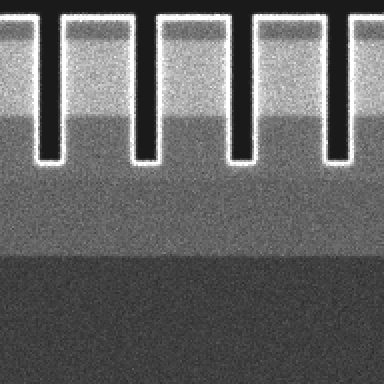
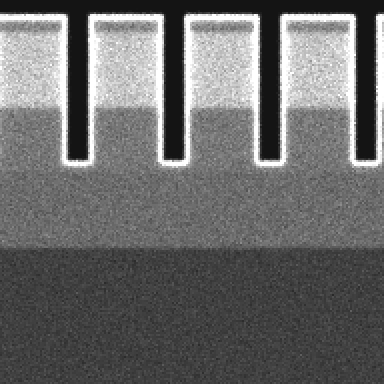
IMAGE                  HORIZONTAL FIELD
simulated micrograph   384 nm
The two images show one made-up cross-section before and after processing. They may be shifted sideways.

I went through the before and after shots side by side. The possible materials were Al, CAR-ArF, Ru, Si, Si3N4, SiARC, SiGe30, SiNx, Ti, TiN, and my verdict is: removed, TiN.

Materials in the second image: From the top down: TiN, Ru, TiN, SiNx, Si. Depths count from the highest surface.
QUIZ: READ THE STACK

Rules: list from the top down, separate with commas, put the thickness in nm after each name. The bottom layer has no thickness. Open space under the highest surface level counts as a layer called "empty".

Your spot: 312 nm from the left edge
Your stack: TiN 16, Ru 76, TiN 64, SiNx 76, Si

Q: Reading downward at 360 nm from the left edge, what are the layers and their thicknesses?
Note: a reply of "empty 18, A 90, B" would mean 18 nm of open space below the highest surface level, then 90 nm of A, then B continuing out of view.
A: empty 146, TiN 10, SiNx 76, Si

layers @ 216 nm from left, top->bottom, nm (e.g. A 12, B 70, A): TiN 16, Ru 76, TiN 64, SiNx 76, Si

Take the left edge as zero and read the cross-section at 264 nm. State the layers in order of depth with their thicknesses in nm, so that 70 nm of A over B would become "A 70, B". empty 146, TiN 10, SiNx 76, Si